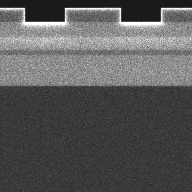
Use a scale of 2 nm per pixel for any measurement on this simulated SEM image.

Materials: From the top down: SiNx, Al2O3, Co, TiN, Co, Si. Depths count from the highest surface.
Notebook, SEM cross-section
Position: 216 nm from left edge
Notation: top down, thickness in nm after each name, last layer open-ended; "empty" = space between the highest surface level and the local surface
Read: SiNx 28, Al2O3 30, Co 26, TiN 10, Co 62, Si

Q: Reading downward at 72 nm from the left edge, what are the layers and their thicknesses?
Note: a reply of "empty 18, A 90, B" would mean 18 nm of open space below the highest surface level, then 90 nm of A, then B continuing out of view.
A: empty 28, Al2O3 30, Co 26, TiN 10, Co 62, Si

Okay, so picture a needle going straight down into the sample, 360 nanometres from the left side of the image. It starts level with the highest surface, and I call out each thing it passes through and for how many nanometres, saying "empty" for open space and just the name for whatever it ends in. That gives SiNx 28, Al2O3 30, Co 26, TiN 10, Co 62, Si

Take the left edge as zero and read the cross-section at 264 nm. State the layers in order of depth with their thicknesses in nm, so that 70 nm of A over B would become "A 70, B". empty 28, Al2O3 30, Co 26, TiN 10, Co 62, Si